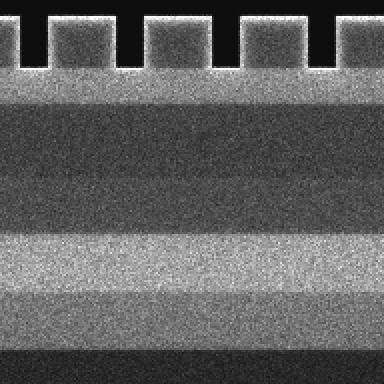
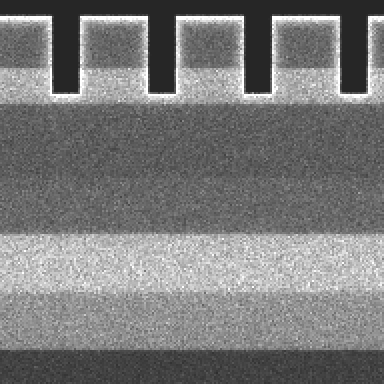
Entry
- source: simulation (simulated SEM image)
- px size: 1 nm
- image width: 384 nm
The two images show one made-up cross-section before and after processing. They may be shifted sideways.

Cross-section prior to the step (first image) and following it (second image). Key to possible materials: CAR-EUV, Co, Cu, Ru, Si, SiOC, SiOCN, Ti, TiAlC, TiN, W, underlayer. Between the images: Ru was removed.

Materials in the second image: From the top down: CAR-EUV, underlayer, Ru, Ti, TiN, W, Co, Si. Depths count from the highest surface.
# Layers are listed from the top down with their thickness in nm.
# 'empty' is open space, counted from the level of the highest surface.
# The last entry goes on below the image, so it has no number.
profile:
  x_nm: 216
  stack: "CAR-EUV 34, underlayer 18, Ru 36, Ti 74, TiN 56, W 58, Co 58, Si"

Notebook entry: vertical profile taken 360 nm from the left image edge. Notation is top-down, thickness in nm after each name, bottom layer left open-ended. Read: empty 78, Ru 10, Ti 74, TiN 56, W 58, Co 58, Si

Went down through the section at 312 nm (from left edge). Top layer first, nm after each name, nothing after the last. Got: CAR-EUV 34, underlayer 18, Ru 36, Ti 74, TiN 56, W 58, Co 58, Si